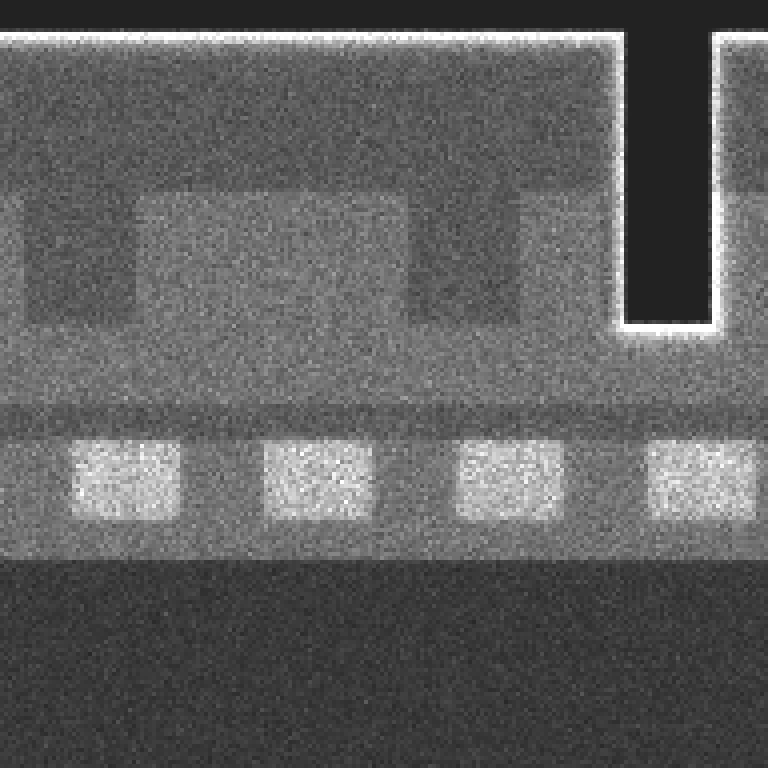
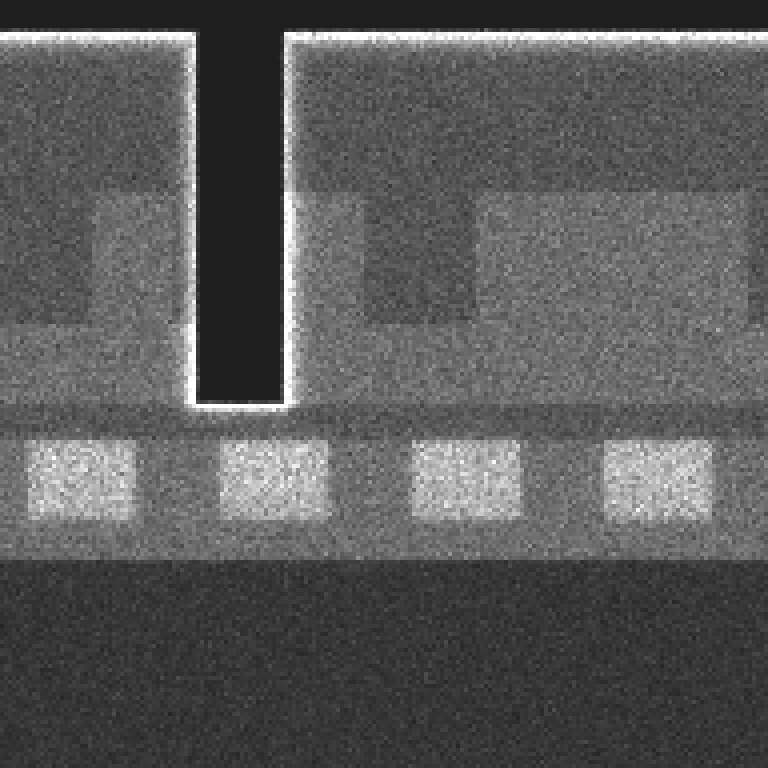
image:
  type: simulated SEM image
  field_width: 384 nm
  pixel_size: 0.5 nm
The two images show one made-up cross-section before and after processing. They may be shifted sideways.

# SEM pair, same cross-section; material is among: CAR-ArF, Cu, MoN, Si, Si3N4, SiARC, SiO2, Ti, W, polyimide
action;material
removed;SiO2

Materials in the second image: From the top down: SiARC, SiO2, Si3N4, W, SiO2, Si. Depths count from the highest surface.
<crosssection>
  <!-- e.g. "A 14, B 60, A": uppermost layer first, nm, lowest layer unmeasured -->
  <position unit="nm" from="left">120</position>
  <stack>empty 186, Si3N4 18, W 40, SiO2 20, Si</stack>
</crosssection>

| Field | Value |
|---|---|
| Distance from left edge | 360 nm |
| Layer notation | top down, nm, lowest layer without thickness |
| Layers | SiARC 80, SiO2 106, Si3N4 18, SiO2 60, Si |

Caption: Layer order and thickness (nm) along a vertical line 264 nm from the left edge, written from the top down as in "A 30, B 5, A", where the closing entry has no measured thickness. SiARC 80, SiO2 106, Si3N4 18, SiO2 60, Si